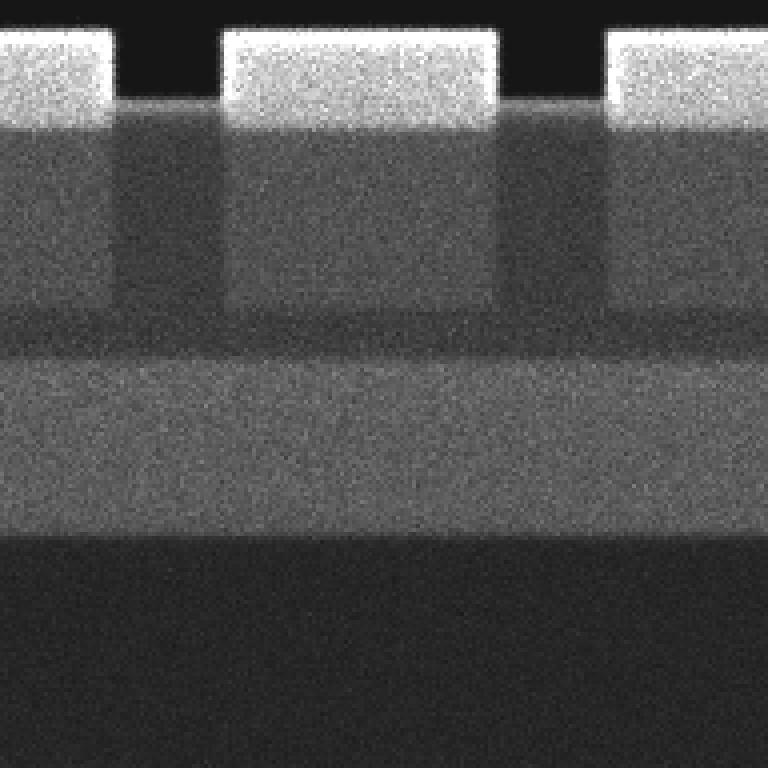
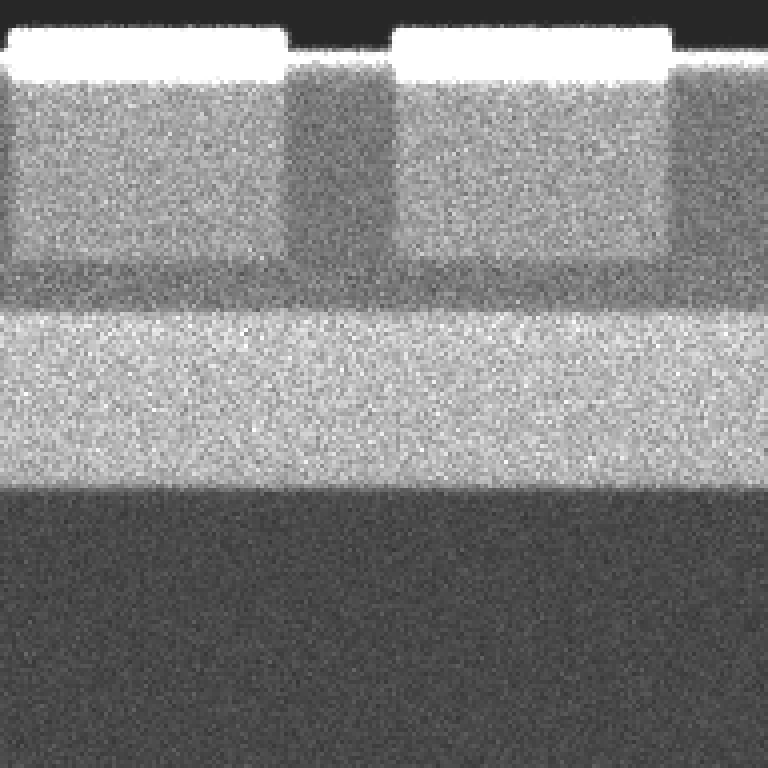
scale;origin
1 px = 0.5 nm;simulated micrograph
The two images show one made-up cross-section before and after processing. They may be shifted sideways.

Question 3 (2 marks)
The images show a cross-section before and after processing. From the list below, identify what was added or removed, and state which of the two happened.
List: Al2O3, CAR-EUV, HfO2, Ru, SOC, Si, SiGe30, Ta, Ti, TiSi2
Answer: HfO2 was removed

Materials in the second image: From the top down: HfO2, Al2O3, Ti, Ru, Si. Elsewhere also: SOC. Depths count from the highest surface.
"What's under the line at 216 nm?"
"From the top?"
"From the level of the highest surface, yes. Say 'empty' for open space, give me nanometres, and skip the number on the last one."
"HfO2 24, Al2O3 90, Ti 26, Ru 88, Si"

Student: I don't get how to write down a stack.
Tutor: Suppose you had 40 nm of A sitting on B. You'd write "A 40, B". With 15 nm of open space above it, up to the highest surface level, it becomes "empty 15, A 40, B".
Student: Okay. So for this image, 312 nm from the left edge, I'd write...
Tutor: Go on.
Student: HfO2 24, Al2O3 90, Ti 26, Ru 88, Si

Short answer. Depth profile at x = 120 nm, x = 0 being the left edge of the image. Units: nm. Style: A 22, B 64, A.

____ HfO2 24, Al2O3 90, Ti 26, Ru 88, Si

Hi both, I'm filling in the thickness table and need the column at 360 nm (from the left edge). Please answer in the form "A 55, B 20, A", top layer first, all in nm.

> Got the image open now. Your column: empty 10, SOC 104, Ti 26, Ru 88, Si